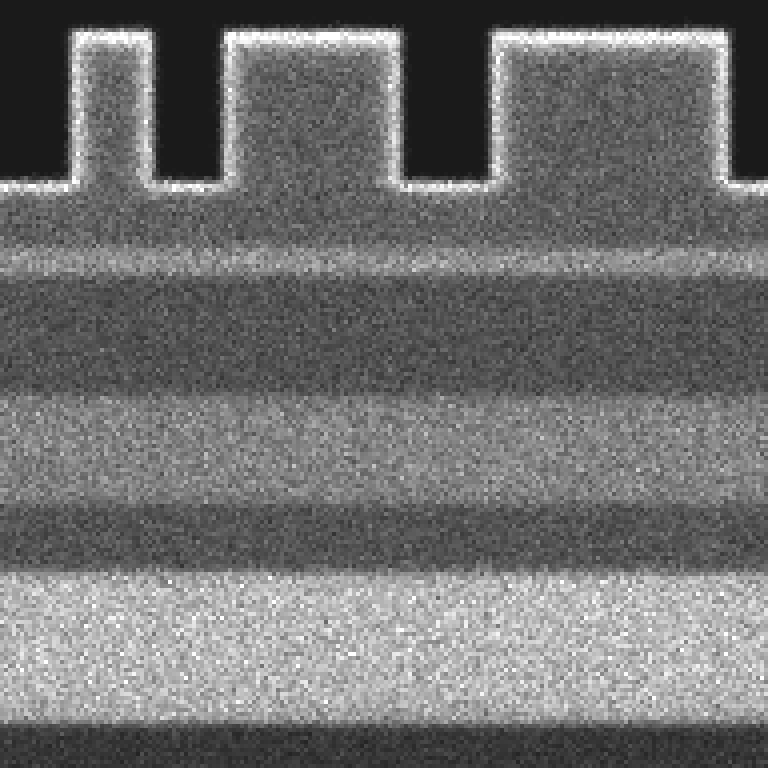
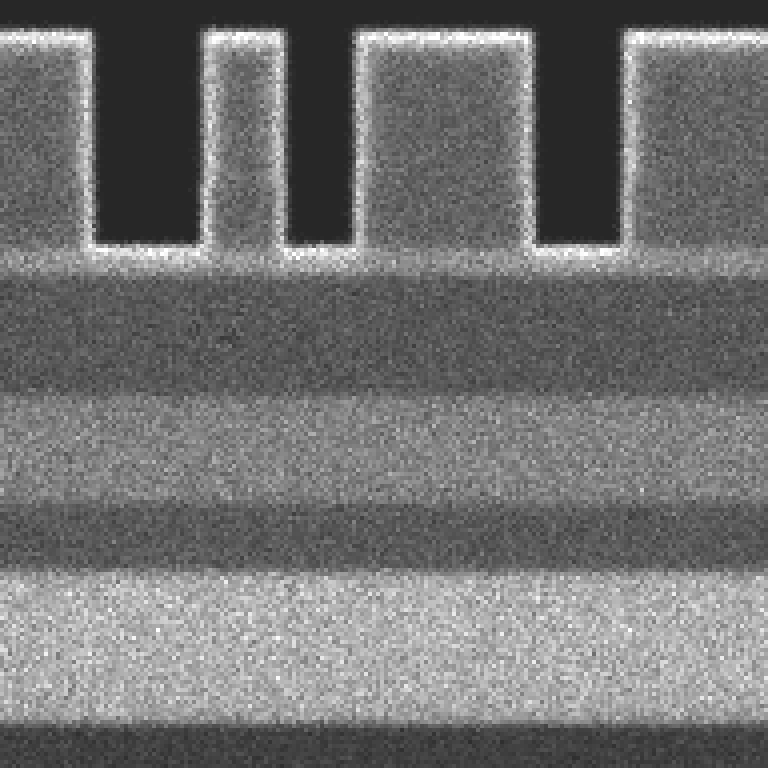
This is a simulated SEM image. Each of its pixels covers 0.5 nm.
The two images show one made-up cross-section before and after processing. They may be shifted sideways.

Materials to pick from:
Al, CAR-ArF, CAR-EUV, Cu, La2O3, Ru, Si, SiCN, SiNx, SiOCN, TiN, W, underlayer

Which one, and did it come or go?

TiN - removed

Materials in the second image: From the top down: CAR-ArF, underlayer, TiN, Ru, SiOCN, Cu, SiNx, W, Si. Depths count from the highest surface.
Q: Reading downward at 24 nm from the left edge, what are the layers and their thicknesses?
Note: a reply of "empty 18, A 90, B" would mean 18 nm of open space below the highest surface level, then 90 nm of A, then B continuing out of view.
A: CAR-ArF 36, underlayer 40, TiN 32, Ru 14, SiOCN 60, Cu 54, SiNx 34, W 76, Si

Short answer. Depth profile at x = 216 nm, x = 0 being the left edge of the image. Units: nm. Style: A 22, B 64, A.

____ CAR-ArF 36, underlayer 40, TiN 32, Ru 14, SiOCN 60, Cu 54, SiNx 34, W 76, Si